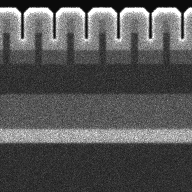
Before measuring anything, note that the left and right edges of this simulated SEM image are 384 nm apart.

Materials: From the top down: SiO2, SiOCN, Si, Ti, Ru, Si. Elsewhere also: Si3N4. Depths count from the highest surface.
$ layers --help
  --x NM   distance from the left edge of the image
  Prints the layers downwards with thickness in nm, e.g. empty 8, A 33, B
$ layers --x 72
SiO2 22, Si3N4 28, Si 122, Ti 70, Ru 28, Si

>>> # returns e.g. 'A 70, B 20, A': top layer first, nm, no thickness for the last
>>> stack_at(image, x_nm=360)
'empty 10, SiO2 74, SiOCN 28, Si 60, Ti 70, Ru 28, Si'